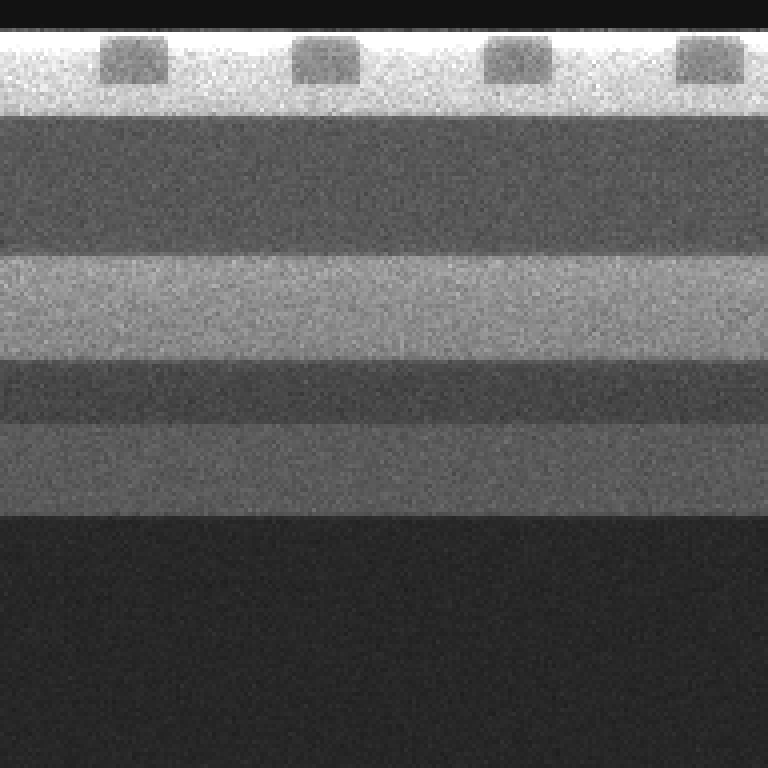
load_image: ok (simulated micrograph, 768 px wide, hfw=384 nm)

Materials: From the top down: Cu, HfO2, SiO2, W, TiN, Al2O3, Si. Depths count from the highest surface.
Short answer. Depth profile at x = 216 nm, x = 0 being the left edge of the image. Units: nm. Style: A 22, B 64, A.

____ HfO2 42, SiO2 70, W 52, TiN 32, Al2O3 46, Si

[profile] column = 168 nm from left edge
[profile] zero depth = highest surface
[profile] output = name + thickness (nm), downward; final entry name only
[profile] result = Cu 26, HfO2 16, SiO2 70, W 52, TiN 32, Al2O3 46, Si